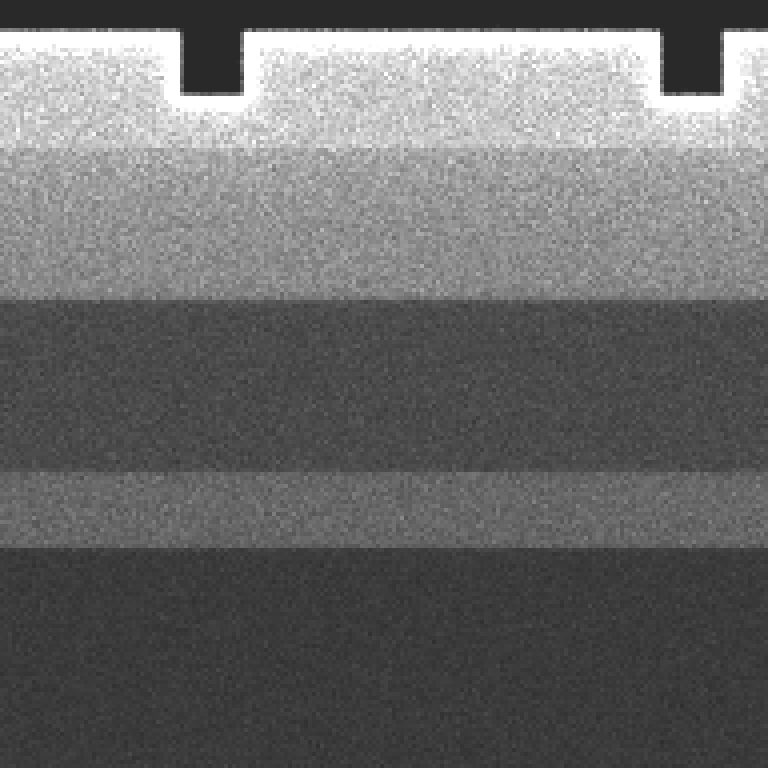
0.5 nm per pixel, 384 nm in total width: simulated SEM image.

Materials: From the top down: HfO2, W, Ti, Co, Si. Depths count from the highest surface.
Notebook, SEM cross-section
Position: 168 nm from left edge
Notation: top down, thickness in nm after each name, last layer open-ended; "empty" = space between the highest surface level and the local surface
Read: HfO2 58, W 76, Ti 86, Co 38, Si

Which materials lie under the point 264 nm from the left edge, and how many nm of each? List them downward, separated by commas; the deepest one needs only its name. HfO2 58, W 76, Ti 86, Co 38, Si